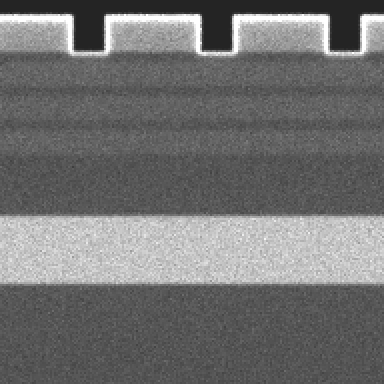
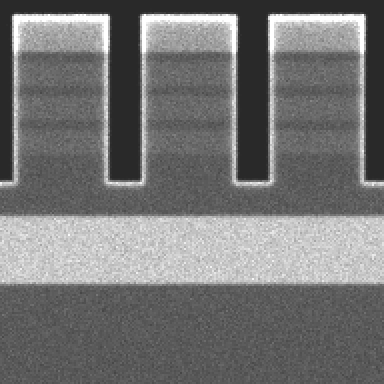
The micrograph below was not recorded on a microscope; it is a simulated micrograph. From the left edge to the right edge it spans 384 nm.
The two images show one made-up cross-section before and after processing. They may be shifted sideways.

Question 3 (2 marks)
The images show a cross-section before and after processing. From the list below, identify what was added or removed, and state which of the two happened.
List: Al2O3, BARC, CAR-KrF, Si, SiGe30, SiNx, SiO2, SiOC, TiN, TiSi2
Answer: Si and SiGe30 was removed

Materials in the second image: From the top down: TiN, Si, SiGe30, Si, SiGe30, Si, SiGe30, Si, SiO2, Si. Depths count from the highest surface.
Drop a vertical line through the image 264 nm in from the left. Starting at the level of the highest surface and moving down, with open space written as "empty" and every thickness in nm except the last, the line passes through empty 166, Si 34, SiO2 68, Si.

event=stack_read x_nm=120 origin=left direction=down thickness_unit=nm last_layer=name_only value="empty 166, Si 34, SiO2 68, Si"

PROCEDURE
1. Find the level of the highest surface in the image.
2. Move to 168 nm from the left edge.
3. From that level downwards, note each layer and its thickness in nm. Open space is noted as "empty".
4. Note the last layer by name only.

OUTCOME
TiN 36, Si 10, SiGe30 24, Si 10, SiGe30 24, Si 10, SiGe30 24, Si 62, SiO2 68, Si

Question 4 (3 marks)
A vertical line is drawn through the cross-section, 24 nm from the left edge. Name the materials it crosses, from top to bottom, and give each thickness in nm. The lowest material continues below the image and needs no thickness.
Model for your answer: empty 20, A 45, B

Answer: TiN 36, Si 10, SiGe30 24, Si 10, SiGe30 24, Si 10, SiGe30 24, Si 62, SiO2 68, Si